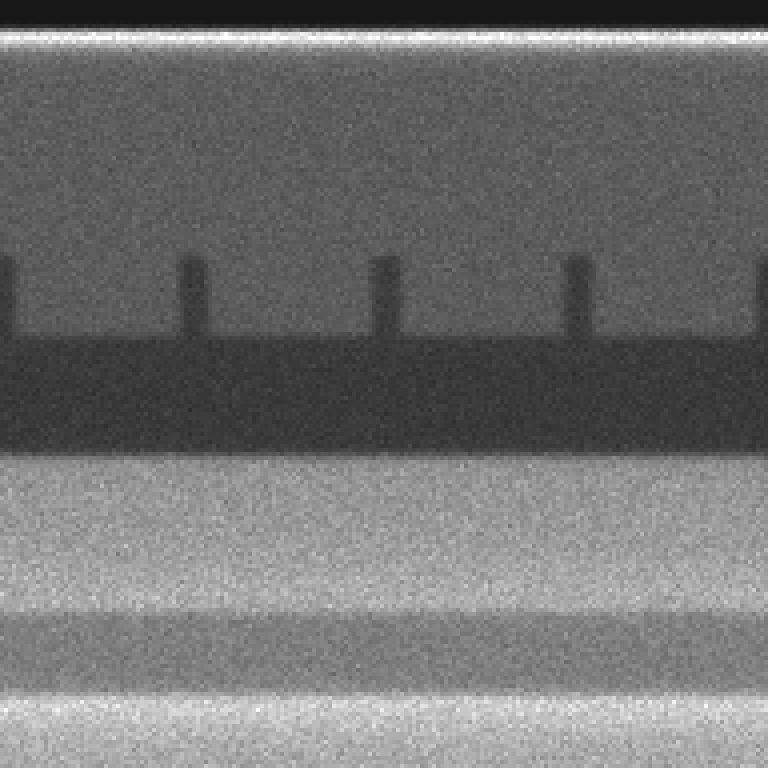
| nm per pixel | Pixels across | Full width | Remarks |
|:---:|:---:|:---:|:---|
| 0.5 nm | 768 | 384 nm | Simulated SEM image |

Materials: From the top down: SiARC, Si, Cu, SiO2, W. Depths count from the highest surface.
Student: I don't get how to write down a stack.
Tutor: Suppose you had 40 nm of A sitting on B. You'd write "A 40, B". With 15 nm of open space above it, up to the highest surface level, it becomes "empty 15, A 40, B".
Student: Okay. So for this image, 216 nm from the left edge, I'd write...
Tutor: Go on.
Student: SiARC 152, Si 60, Cu 78, SiO2 42, W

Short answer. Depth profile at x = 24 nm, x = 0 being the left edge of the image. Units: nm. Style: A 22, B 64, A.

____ SiARC 152, Si 60, Cu 78, SiO2 42, W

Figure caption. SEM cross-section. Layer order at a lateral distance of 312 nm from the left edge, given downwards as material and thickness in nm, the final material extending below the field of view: SiARC 152, Si 60, Cu 78, SiO2 42, W